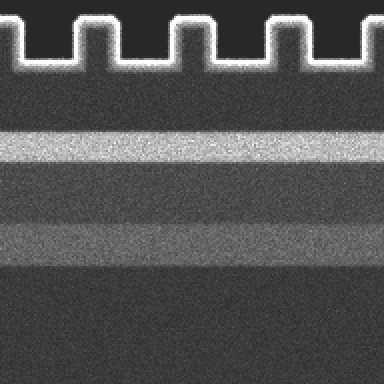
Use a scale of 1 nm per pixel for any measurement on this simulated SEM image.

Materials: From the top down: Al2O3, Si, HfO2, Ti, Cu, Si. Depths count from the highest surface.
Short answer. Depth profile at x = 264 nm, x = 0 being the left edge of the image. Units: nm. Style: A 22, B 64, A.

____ empty 44, Al2O3 12, Si 60, HfO2 30, Ti 62, Cu 42, Si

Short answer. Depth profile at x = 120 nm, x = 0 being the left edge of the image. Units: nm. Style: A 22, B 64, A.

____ empty 44, Al2O3 12, Si 60, HfO2 30, Ti 62, Cu 42, Si